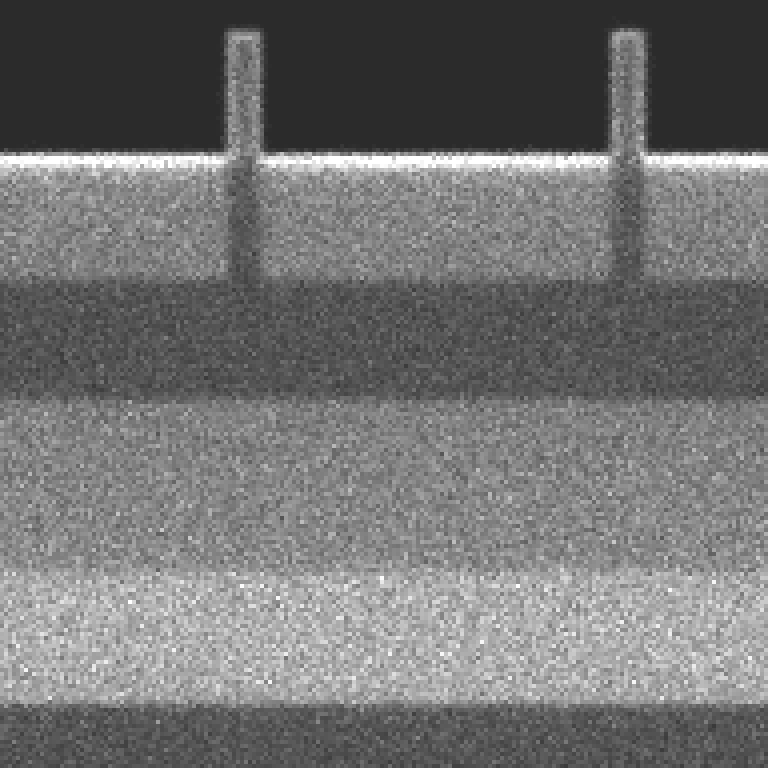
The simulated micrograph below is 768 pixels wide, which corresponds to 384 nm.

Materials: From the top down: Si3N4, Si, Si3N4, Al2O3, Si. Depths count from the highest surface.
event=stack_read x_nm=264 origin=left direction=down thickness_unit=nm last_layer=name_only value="empty 62, Si3N4 62, Si 60, Si3N4 86, Al2O3 66, Si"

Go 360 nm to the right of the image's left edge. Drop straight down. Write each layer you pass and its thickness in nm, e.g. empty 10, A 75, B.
empty 62, Si3N4 62, Si 60, Si3N4 86, Al2O3 66, Si